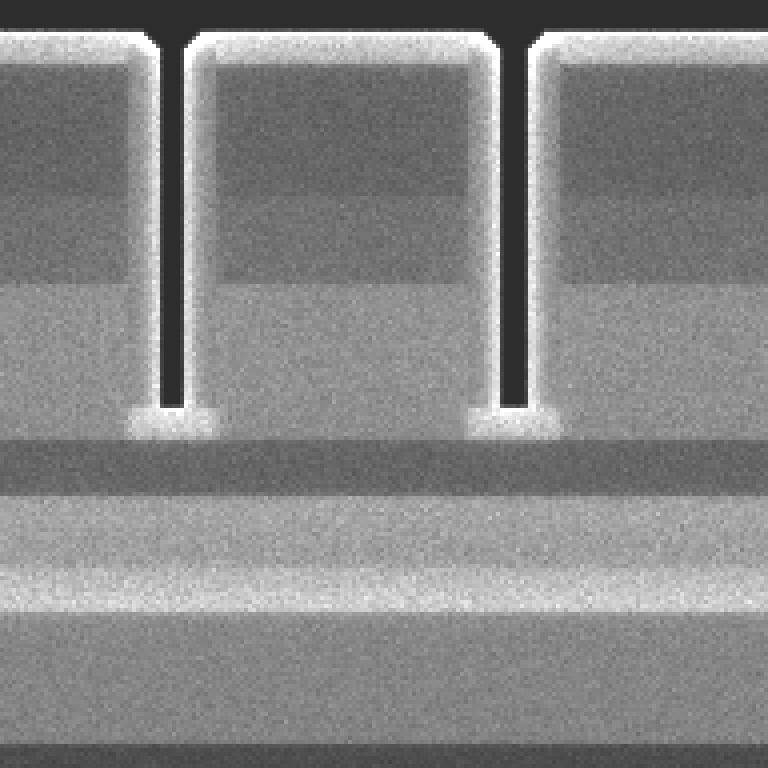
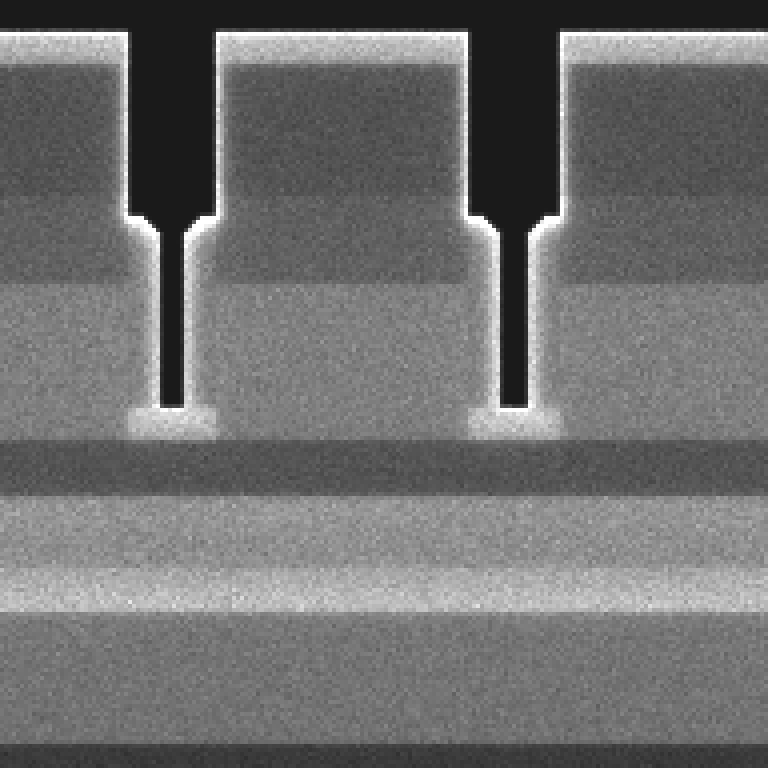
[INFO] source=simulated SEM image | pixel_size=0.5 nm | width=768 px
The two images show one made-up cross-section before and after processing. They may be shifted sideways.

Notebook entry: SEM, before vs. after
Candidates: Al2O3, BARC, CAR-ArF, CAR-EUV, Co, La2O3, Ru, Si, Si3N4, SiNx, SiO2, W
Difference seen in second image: SiO2 removed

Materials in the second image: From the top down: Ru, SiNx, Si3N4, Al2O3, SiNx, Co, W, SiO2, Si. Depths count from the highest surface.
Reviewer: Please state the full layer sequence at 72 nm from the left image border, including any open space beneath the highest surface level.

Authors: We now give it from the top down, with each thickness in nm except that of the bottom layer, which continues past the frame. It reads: empty 94, SiO2 94, Ru 16, SiNx 28, Co 36, W 22, SiO2 66, Si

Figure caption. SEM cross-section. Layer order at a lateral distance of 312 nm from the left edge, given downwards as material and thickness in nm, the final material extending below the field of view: Ru 16, SiNx 66, Si3N4 44, Al2O3 78, SiNx 28, Co 36, W 22, SiO2 66, Si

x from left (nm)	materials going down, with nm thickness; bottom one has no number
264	empty 100, SiO2 88, Ru 16, SiNx 28, Co 36, W 22, SiO2 66, Si